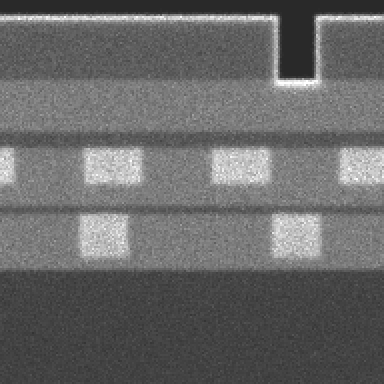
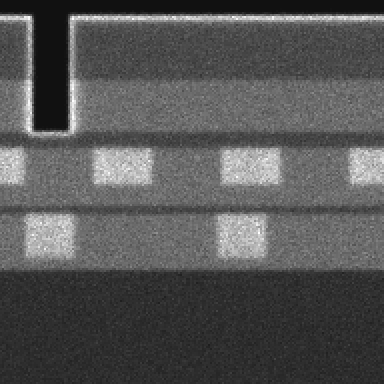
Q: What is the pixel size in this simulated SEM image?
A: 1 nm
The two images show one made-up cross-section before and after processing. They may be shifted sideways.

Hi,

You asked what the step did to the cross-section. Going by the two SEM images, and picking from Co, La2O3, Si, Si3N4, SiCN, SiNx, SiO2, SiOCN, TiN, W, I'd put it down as SiO2, removed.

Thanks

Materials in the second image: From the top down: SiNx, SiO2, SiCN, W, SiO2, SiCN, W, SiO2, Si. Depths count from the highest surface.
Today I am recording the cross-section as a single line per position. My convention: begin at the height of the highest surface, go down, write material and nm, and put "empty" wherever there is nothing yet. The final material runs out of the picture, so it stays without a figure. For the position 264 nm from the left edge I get SiNx 64, SiO2 52, SiCN 16, W 36, SiO2 22, SiCN 8, W 44, SiO2 12, Si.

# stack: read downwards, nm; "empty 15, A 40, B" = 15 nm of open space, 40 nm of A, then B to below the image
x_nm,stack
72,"SiNx 64, SiO2 52, SiCN 16, SiO2 58, SiCN 8, W 44, SiO2 12, Si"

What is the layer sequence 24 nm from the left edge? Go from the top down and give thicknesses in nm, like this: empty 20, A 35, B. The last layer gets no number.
SiNx 64, SiO2 52, SiCN 16, SiO2 58, SiCN 8, SiO2 56, Si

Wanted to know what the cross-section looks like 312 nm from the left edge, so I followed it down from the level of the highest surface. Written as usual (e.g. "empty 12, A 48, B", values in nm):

SiNx 64, SiO2 52, SiCN 16, SiO2 58, SiCN 8, SiO2 56, Si